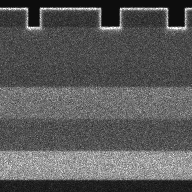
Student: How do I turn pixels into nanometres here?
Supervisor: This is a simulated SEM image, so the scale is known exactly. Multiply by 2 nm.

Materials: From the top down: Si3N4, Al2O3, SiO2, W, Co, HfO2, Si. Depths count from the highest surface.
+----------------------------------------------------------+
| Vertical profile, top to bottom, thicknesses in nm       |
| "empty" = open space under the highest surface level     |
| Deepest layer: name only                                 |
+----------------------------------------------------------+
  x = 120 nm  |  Si3N4 38, Al2O3 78, SiO2 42, W 64, Co 64, HfO2 58, Si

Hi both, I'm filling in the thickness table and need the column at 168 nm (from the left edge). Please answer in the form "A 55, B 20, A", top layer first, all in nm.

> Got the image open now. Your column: Si3N4 38, Al2O3 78, SiO2 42, W 64, Co 64, HfO2 58, Si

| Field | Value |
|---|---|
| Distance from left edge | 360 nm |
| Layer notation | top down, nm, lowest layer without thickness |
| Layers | empty 38, Al2O3 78, SiO2 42, W 64, Co 64, HfO2 58, Si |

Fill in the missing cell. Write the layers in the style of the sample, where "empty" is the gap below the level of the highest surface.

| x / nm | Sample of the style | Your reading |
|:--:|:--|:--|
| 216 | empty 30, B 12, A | empty 38, Al2O3 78, SiO2 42, W 64, Co 64, HfO2 58, Si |